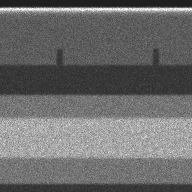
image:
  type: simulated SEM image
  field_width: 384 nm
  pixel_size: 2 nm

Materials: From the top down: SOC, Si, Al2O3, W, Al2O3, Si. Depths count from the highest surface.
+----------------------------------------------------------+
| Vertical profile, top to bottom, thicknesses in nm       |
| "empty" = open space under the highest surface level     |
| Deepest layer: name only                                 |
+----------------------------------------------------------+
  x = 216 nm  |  SOC 114, Si 60, Al2O3 46, W 80, Al2O3 52, Si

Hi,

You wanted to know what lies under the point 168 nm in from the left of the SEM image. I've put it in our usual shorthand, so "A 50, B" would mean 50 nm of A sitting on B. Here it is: SOC 114, Si 60, Al2O3 46, W 80, Al2O3 52, Si